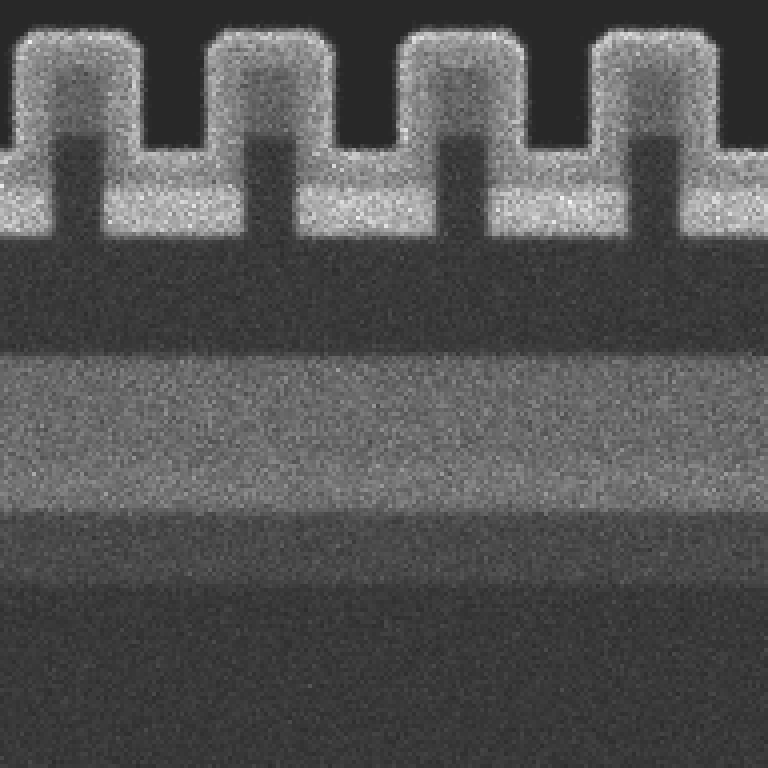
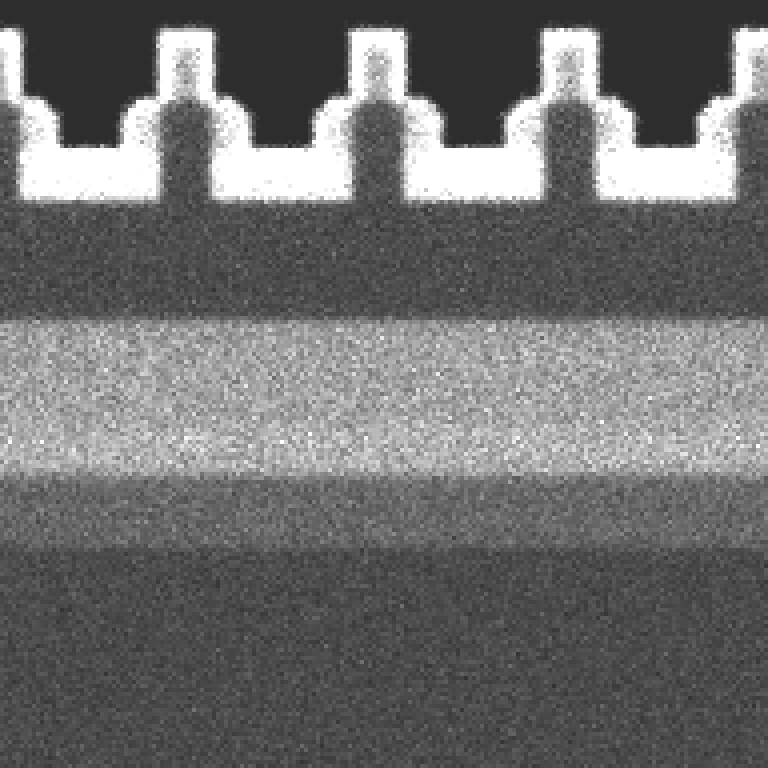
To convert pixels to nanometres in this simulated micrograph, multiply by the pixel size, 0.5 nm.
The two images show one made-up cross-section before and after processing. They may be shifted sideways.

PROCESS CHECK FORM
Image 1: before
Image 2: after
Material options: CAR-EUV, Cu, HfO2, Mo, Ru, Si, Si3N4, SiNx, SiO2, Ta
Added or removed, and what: removed, Ru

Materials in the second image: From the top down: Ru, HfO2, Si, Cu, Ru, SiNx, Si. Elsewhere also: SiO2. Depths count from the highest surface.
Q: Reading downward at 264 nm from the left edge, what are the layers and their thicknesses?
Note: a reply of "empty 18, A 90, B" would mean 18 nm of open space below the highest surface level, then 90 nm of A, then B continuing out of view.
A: empty 34, Ru 26, HfO2 24, Si 60, Cu 54, Ru 24, SiNx 36, Si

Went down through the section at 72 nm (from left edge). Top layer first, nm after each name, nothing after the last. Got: empty 34, Ru 26, HfO2 24, Si 60, Cu 54, Ru 24, SiNx 36, Si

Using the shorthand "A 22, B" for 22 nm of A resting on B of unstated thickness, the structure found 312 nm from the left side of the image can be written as empty 40, Ru 20, HfO2 24, Si 60, Cu 54, Ru 24, SiNx 36, Si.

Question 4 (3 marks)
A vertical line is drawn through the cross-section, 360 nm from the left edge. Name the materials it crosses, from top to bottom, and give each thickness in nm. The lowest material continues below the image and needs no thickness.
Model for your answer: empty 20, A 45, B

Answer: empty 34, Ru 26, HfO2 24, Si 60, Cu 54, Ru 24, SiNx 36, Si